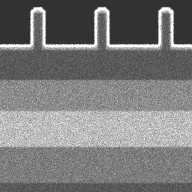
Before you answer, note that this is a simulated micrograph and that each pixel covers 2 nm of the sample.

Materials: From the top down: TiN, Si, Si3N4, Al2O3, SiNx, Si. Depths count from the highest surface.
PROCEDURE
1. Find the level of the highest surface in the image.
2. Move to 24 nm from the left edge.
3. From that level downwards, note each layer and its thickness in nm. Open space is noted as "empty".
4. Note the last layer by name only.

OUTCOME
empty 74, TiN 10, Si 60, Si3N4 62, Al2O3 72, SiNx 72, Si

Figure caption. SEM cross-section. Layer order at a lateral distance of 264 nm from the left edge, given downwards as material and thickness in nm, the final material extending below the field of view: empty 74, TiN 10, Si 60, Si3N4 62, Al2O3 72, SiNx 72, Si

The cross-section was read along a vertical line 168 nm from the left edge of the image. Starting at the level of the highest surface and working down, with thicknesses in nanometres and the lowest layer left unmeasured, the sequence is empty 74, TiN 10, Si 60, Si3N4 62, Al2O3 72, SiNx 72, Si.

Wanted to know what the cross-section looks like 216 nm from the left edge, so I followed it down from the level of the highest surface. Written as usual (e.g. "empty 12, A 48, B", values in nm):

empty 6, TiN 78, Si 60, Si3N4 62, Al2O3 72, SiNx 72, Si